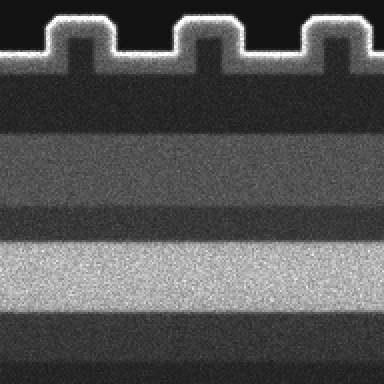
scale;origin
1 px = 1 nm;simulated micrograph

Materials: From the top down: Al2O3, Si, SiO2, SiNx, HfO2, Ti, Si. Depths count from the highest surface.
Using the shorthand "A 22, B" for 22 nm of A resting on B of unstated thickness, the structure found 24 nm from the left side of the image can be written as empty 36, Al2O3 22, Si 60, SiO2 72, SiNx 36, HfO2 70, Ti 50, Si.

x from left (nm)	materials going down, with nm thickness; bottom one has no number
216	Al2O3 22, Si 96, SiO2 72, SiNx 36, HfO2 70, Ti 50, Si